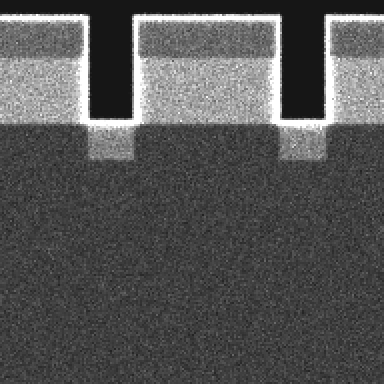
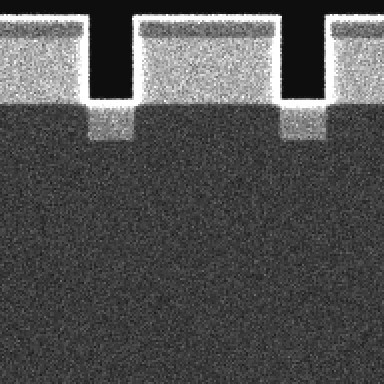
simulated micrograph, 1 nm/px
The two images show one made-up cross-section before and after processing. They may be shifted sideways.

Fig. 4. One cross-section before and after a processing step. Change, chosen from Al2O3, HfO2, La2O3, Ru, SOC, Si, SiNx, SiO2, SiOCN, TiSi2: SiNx removed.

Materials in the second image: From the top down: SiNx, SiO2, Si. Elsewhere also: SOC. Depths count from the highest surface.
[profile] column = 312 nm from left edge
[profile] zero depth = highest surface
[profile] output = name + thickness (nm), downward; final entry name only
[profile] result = empty 84, SOC 40, Si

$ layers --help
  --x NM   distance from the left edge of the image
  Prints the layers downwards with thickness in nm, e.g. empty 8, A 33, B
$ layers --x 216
SiNx 22, SiO2 66, Si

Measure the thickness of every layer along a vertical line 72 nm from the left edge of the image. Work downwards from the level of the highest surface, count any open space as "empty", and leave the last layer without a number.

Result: SiNx 22, SiO2 66, Si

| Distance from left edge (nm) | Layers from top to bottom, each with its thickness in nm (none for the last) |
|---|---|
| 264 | SiNx 22, SiO2 66, Si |